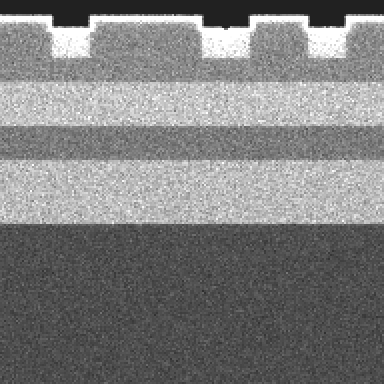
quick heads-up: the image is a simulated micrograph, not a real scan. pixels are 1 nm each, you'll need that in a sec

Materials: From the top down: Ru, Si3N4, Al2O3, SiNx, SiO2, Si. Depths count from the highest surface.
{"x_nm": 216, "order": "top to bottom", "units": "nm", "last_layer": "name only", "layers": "empty 12, Ru 30, Si3N4 24, Al2O3 44, SiNx 34, SiO2 64, Si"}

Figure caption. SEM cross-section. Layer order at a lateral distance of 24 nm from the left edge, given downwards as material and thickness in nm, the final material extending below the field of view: Si3N4 66, Al2O3 44, SiNx 34, SiO2 64, Si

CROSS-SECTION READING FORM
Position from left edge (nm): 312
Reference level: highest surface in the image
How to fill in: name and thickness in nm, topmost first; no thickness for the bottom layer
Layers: empty 12, Ru 30, Si3N4 24, Al2O3 44, SiNx 34, SiO2 64, Si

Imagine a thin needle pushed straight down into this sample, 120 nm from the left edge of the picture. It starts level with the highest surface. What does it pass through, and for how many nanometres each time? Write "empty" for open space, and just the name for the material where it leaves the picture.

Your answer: Si3N4 66, Al2O3 44, SiNx 34, SiO2 64, Si